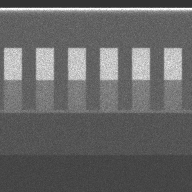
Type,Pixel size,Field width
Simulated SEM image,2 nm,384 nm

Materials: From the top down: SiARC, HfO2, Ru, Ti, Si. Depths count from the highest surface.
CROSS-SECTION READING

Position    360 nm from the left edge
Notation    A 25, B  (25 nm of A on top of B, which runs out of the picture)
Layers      SiARC 80, HfO2 64, Ru 66, Ti 84, Si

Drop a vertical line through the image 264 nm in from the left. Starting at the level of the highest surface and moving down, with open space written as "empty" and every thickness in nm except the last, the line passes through SiARC 80, HfO2 64, Ru 66, Ti 84, Si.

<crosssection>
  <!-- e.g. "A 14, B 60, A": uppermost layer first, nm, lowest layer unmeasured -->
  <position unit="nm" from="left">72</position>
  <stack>SiARC 80, HfO2 64, Ru 66, Ti 84, Si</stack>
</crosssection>